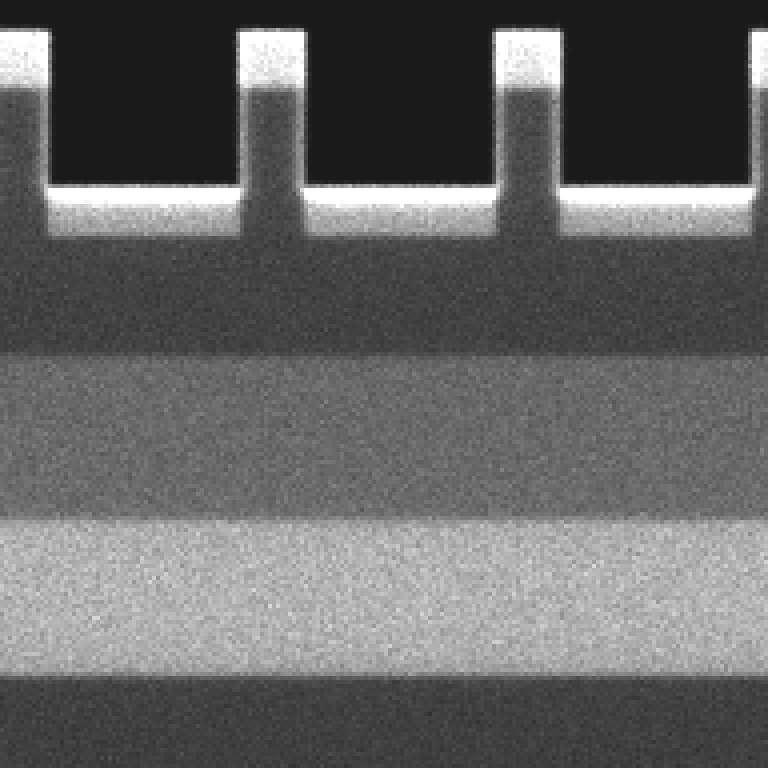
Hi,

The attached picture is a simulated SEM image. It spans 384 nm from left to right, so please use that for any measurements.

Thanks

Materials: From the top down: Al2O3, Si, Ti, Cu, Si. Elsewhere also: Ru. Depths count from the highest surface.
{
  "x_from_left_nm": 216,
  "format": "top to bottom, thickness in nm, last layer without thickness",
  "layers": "empty 78, Al2O3 24, Si 60, Ti 82, Cu 78, Si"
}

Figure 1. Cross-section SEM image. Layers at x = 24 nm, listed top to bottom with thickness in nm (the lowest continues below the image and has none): empty 78, Al2O3 24, Si 60, Ti 82, Cu 78, Si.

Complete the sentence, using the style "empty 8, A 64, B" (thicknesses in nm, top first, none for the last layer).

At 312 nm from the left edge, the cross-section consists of empty 78, Al2O3 24, Si 60, Ti 82, Cu 78, Si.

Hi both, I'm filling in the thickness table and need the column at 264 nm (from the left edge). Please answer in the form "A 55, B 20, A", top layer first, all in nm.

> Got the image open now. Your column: Ru 28, Si 134, Ti 82, Cu 78, Si